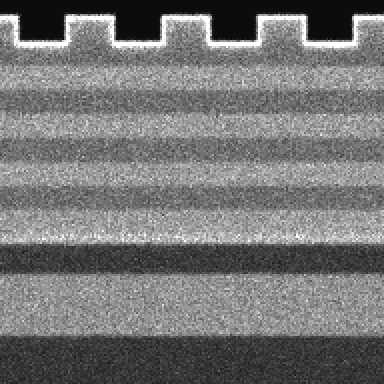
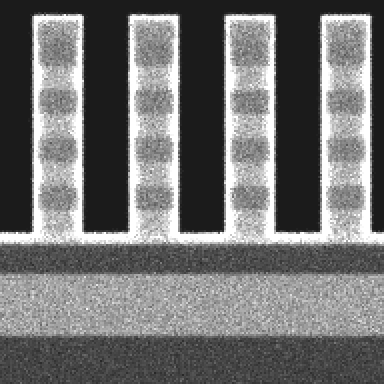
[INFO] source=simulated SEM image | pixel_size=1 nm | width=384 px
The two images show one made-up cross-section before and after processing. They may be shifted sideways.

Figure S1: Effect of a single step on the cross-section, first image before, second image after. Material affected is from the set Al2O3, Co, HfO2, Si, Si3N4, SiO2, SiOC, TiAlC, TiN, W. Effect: removed Al2O3 and Si3N4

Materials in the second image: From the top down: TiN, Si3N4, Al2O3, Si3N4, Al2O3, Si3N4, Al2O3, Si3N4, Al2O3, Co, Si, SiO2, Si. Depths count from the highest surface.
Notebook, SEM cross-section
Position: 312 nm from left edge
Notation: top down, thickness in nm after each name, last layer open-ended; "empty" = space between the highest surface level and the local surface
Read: empty 218, Co 10, Si 30, SiO2 62, Si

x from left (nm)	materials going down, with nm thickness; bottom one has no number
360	TiN 26, Si3N4 24, Al2O3 24, Si3N4 24, Al2O3 24, Si3N4 24, Al2O3 24, Si3N4 24, Al2O3 24, Co 10, Si 30, SiO2 62, Si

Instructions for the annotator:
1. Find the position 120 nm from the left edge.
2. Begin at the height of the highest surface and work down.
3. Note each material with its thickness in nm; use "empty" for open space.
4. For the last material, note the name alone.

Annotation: empty 218, Co 10, Si 30, SiO2 62, Si